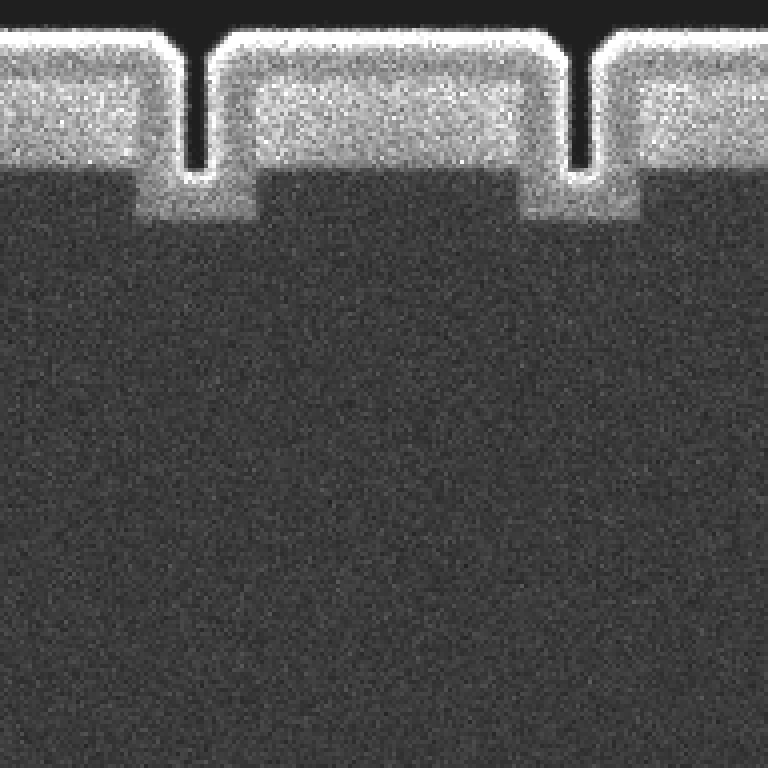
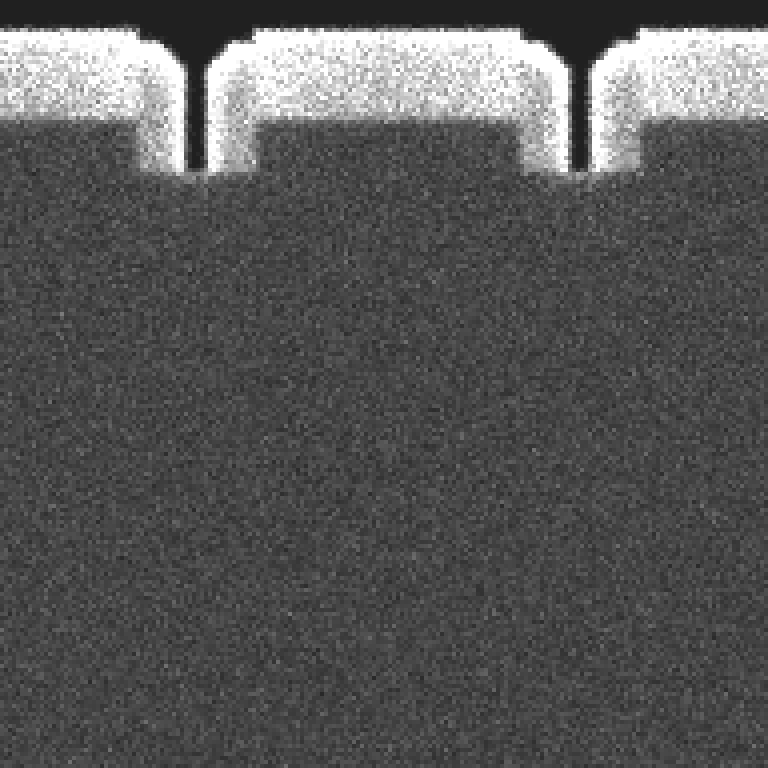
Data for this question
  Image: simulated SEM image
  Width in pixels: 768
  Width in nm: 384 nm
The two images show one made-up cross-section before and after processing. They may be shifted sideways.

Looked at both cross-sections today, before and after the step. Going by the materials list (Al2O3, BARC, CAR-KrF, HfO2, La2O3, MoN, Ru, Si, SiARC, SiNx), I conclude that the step removed Al2O3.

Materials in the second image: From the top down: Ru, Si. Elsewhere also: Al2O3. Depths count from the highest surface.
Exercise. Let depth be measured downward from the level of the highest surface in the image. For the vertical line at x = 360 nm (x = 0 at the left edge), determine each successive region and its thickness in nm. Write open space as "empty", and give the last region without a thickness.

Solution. Ru 44, Si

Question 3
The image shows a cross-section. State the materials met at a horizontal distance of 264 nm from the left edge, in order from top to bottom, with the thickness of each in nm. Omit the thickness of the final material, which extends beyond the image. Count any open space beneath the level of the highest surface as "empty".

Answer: empty 6, Al2O3 64, Si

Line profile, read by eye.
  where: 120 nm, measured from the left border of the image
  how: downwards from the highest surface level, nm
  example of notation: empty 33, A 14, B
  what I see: empty 6, Al2O3 64, Si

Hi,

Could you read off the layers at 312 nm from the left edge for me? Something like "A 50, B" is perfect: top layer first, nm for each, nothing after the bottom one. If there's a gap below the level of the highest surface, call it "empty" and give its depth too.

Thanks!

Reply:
empty 6, Al2O3 64, Si